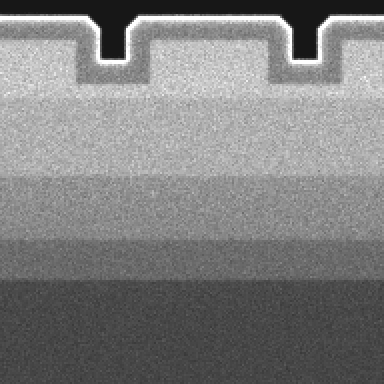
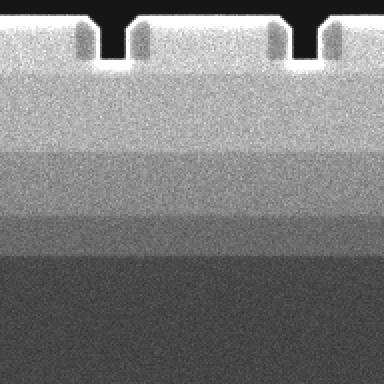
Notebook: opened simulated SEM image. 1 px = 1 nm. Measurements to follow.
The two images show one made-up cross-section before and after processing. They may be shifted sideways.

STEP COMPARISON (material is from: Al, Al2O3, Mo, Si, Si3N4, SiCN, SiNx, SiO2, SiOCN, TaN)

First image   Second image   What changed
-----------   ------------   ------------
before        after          SiNx, removed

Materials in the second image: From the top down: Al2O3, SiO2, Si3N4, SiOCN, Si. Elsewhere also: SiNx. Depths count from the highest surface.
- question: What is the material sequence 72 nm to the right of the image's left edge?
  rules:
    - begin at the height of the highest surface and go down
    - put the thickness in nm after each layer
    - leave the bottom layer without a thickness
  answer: Al2O3 58, SiO2 78, Si3N4 64, SiOCN 40, Si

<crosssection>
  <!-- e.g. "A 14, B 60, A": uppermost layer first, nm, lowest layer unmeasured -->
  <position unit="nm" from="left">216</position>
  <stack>Al2O3 58, SiO2 78, Si3N4 64, SiOCN 40, Si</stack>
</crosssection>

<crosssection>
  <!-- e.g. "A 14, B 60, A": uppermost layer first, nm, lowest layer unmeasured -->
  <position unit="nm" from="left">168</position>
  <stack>Al2O3 58, SiO2 78, Si3N4 64, SiOCN 40, Si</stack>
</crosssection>